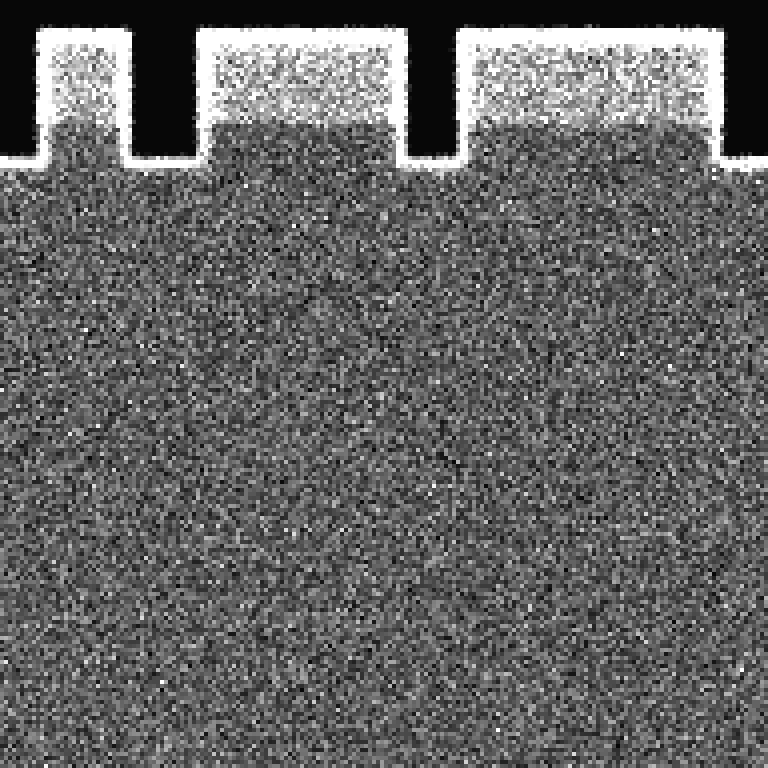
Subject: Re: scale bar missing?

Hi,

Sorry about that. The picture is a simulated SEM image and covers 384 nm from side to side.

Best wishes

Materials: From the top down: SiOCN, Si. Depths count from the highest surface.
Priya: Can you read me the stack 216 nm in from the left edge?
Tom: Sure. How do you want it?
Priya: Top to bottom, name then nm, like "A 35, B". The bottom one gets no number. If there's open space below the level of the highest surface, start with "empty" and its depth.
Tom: empty 64, Si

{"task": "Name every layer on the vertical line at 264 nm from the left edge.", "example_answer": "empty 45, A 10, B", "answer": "SiOCN 46, Si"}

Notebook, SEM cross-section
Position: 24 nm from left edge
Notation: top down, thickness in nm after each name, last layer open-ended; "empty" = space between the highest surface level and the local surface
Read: SiOCN 46, Si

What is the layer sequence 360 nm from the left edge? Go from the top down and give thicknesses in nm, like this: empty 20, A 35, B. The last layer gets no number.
empty 64, Si